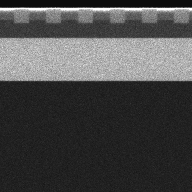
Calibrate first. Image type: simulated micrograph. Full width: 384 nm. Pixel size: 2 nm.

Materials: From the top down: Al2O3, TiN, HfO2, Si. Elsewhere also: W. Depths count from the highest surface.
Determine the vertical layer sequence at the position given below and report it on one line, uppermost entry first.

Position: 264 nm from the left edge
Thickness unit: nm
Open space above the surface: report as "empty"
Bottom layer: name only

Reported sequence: Al2O3 24, TiN 36, HfO2 86, Si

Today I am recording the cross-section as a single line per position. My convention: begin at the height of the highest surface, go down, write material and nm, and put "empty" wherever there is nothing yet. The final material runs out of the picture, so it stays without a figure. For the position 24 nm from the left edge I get Al2O3 24, TiN 36, HfO2 86, Si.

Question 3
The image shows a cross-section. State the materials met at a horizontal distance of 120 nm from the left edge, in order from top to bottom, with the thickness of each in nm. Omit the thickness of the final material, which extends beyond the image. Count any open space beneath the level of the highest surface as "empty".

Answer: W 30, TiN 30, HfO2 86, Si